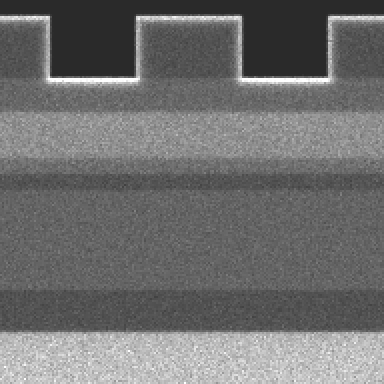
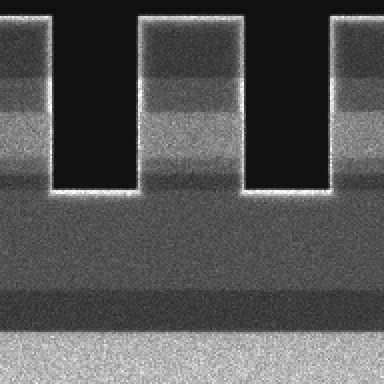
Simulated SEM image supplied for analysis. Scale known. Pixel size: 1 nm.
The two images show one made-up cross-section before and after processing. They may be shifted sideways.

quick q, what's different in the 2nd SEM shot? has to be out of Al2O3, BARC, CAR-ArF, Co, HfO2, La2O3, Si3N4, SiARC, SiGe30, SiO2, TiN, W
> Al2O3 and Co and TiN and W removed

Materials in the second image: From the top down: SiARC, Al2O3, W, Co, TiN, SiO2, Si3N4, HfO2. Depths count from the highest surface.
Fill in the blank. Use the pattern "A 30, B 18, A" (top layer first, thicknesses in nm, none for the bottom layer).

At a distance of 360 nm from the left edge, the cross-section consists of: SiARC 62, Al2O3 34, W 46, Co 16, TiN 16, SiO2 100, Si3N4 42, HfO2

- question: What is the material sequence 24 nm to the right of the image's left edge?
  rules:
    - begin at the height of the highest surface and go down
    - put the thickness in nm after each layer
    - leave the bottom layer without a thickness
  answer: SiARC 62, Al2O3 34, W 46, Co 16, TiN 16, SiO2 100, Si3N4 42, HfO2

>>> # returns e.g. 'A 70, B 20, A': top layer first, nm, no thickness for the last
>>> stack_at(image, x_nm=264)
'empty 174, SiO2 100, Si3N4 42, HfO2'